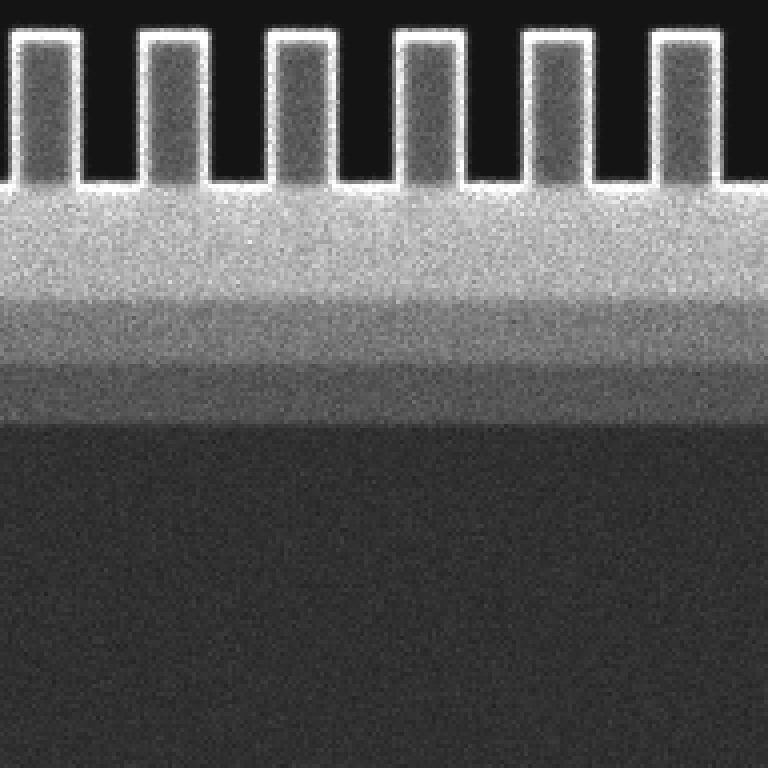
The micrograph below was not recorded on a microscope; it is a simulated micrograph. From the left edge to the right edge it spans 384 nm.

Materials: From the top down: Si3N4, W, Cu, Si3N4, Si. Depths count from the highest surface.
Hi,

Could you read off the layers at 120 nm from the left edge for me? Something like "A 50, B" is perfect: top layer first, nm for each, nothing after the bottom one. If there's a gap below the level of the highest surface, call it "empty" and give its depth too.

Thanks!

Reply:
empty 76, W 58, Cu 32, Si3N4 30, Si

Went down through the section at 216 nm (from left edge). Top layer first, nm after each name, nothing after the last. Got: Si3N4 76, W 58, Cu 32, Si3N4 30, Si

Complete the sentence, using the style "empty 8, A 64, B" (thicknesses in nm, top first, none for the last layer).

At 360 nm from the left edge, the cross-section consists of empty 76, W 58, Cu 32, Si3N4 30, Si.